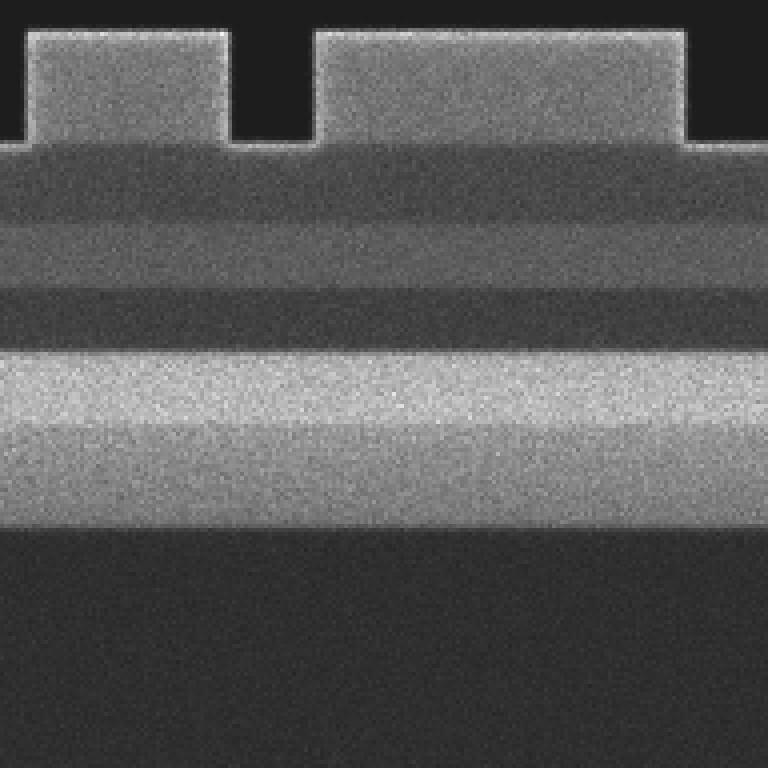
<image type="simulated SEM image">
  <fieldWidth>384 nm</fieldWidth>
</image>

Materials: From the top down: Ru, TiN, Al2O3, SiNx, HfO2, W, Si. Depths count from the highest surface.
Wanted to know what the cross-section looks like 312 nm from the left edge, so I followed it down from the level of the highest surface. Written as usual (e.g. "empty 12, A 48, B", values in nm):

Ru 56, TiN 40, Al2O3 32, SiNx 32, HfO2 36, W 52, Si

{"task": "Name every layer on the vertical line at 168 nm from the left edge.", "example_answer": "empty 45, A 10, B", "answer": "Ru 56, TiN 40, Al2O3 32, SiNx 32, HfO2 36, W 52, Si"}